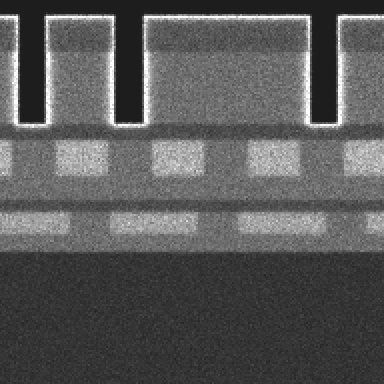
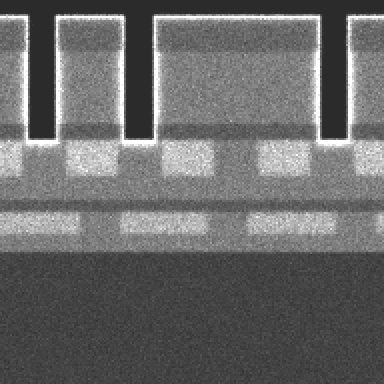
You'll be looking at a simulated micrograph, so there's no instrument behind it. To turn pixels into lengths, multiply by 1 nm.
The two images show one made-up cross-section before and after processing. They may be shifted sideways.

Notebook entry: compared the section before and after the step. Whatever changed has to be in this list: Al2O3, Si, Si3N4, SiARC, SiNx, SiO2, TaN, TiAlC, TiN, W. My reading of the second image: SiNx removed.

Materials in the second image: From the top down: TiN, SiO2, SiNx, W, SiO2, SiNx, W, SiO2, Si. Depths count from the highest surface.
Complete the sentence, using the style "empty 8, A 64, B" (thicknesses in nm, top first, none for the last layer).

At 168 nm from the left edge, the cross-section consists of TiN 36, SiO2 72, SiNx 16, W 36, SiO2 24, SiNx 12, W 22, SiO2 18, Si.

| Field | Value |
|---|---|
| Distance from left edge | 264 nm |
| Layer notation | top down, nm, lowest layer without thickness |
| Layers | TiN 36, SiO2 72, SiNx 16, W 36, SiO2 24, SiNx 12, W 22, SiO2 18, Si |